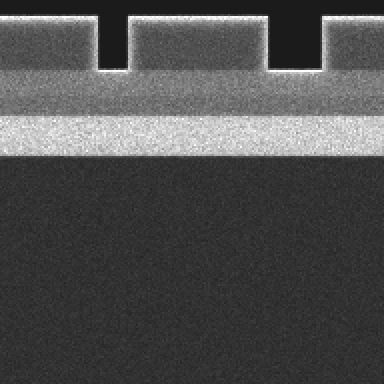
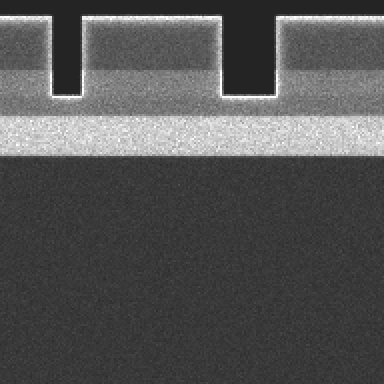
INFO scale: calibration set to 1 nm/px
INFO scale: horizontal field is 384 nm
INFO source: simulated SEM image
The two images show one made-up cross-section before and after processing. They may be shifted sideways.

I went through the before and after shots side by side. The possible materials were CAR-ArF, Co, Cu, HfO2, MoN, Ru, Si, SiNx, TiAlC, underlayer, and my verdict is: removed, Ru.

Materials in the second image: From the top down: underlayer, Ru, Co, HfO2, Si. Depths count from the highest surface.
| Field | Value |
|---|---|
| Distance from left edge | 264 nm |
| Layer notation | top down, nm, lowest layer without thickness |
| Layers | empty 80, Co 20, HfO2 40, Si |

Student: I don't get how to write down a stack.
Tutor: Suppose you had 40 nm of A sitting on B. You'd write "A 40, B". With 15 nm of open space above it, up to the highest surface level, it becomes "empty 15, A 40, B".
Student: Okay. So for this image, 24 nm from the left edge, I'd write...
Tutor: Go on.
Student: underlayer 54, Ru 26, Co 20, HfO2 40, Si